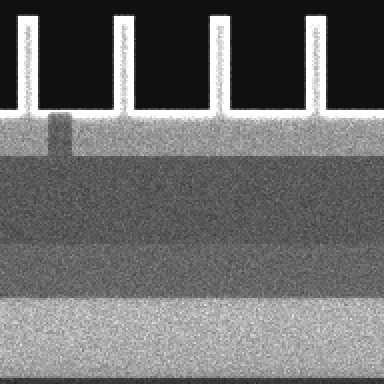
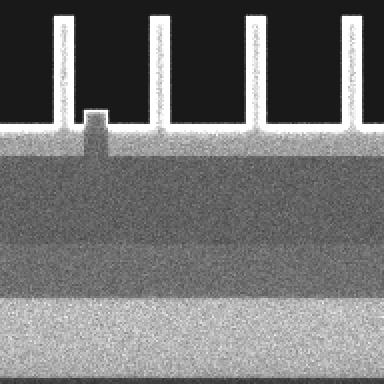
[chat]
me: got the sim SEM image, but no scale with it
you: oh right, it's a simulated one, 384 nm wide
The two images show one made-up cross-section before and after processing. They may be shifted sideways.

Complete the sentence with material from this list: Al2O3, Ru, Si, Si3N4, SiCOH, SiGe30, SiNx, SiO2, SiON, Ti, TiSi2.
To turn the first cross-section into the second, Al2O3 must be removed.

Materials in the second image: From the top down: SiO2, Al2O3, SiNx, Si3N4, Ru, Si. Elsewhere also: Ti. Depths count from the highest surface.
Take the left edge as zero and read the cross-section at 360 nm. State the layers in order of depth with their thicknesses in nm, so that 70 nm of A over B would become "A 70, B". SiO2 94, Al2O3 46, SiNx 88, Si3N4 54, Ru 80, Si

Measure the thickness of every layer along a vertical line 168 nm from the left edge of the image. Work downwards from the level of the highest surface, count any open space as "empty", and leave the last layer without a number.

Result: SiO2 94, Al2O3 46, SiNx 88, Si3N4 54, Ru 80, Si